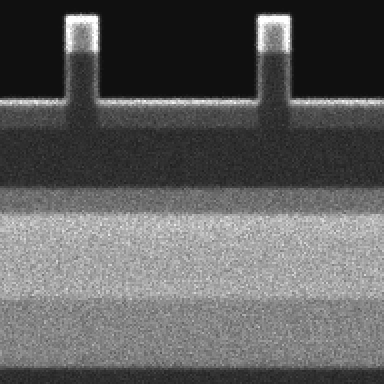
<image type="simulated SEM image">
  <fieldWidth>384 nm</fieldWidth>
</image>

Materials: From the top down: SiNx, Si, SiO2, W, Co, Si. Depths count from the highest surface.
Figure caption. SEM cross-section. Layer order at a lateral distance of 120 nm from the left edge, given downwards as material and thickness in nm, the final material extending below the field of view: empty 84, SiNx 28, Si 60, SiO2 26, W 84, Co 70, Si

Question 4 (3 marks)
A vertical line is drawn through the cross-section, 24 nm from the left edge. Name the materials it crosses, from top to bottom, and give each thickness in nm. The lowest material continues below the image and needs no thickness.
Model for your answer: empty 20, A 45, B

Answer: empty 84, SiNx 28, Si 60, SiO2 26, W 84, Co 70, Si